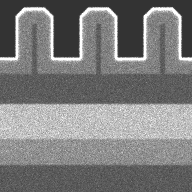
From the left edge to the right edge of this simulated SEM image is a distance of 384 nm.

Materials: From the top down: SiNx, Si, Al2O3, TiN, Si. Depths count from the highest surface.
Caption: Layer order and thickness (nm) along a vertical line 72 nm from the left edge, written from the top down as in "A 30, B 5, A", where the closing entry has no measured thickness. SiNx 32, Si 160, Al2O3 70, TiN 52, Si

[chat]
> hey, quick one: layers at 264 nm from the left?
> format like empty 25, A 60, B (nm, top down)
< empty 100, SiNx 32, Si 60, Al2O3 70, TiN 52, Si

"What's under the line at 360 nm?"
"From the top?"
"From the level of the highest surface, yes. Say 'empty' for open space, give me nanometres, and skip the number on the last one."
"empty 16, SiNx 116, Si 60, Al2O3 70, TiN 52, Si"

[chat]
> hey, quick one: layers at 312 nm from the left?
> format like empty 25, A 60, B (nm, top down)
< SiNx 132, Si 60, Al2O3 70, TiN 52, Si